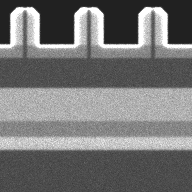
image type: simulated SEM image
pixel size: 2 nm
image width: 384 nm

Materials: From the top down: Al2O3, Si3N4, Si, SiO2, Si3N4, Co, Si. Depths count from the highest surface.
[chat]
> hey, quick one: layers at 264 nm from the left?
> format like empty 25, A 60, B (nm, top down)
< empty 74, Si3N4 26, Si 60, SiO2 66, Si3N4 32, Co 26, Si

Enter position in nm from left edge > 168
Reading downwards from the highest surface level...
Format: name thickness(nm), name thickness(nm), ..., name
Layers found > Al2O3 74, Si3N4 26, Si 60, SiO2 66, Si3N4 32, Co 26, Si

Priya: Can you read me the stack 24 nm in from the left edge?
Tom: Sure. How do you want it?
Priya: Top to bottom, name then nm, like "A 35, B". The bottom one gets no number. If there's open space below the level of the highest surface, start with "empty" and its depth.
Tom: empty 10, Al2O3 64, Si3N4 26, Si 60, SiO2 66, Si3N4 32, Co 26, Si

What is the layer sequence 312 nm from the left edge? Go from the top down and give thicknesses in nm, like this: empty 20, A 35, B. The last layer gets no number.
Al2O3 74, Si3N4 26, Si 60, SiO2 66, Si3N4 32, Co 26, Si